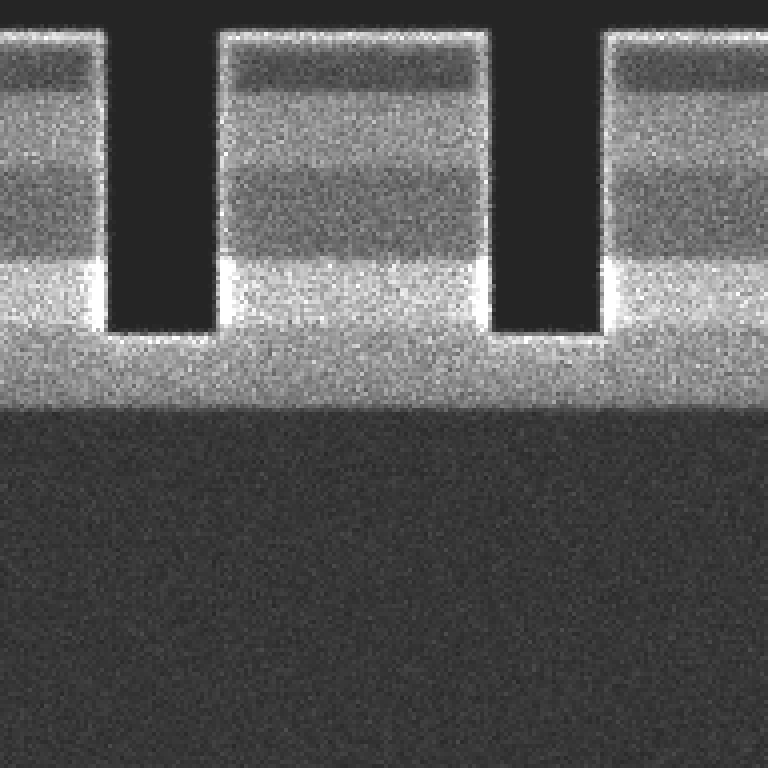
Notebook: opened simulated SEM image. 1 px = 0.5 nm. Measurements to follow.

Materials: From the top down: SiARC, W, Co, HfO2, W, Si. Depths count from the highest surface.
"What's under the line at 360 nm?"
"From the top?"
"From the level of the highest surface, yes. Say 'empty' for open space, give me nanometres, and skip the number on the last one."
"SiARC 30, W 38, Co 46, HfO2 32, W 42, Si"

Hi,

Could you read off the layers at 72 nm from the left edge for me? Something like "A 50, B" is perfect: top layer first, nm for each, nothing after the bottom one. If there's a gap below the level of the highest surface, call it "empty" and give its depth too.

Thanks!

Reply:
empty 152, W 36, Si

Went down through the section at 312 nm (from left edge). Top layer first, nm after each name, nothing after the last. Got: SiARC 30, W 38, Co 46, HfO2 32, W 42, Si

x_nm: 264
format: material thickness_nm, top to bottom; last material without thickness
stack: empty 152, W 36, Si